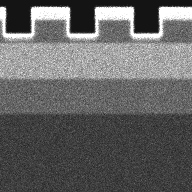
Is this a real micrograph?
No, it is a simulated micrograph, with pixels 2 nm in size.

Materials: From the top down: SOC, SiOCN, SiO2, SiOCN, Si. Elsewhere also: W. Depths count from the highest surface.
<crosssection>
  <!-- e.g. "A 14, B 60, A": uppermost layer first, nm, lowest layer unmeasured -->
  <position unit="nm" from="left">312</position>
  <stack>empty 52, SOC 12, SiOCN 6, SiO2 72, SiOCN 70, Si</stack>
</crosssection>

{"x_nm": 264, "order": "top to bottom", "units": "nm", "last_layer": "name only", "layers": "W 24, SiOCN 46, SiO2 72, SiOCN 70, Si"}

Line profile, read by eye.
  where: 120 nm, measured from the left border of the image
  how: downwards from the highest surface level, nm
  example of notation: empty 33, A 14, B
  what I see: W 24, SiOCN 46, SiO2 72, SiOCN 70, Si